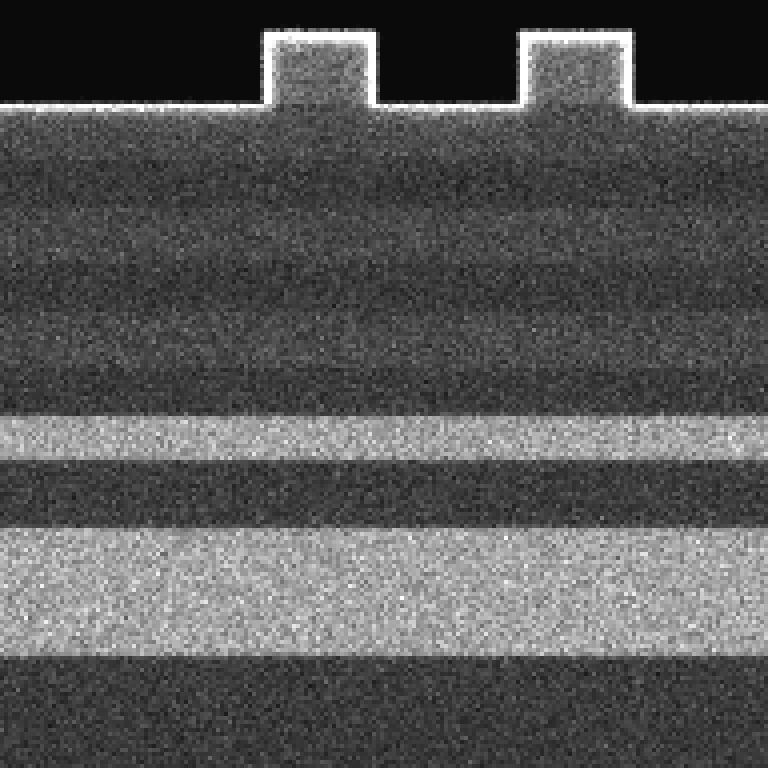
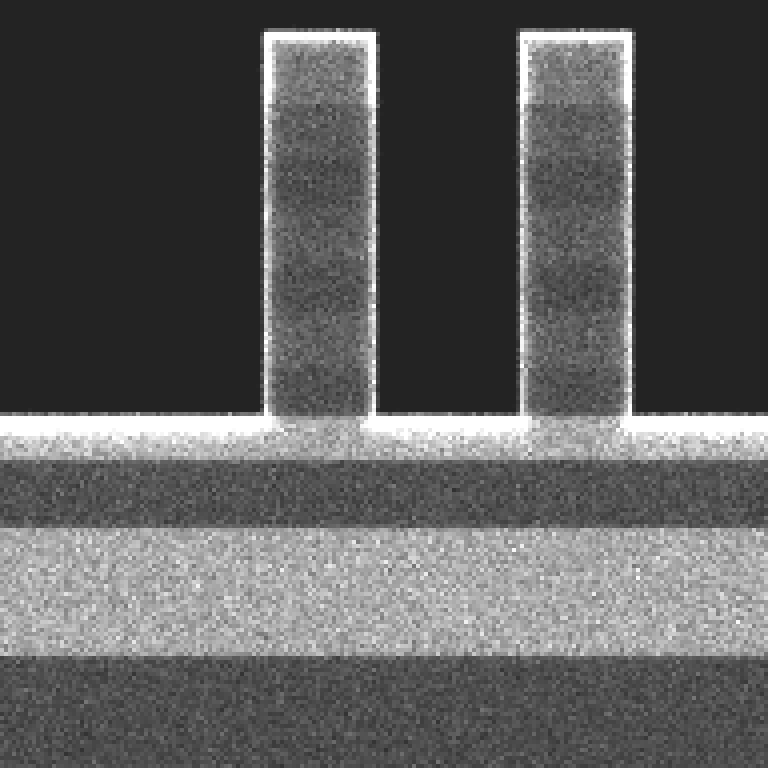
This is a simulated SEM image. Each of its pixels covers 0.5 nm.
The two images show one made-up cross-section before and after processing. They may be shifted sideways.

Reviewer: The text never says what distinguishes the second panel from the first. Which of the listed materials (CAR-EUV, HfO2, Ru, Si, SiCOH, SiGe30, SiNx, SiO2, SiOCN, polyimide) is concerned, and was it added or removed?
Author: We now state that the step removed Si and SiGe30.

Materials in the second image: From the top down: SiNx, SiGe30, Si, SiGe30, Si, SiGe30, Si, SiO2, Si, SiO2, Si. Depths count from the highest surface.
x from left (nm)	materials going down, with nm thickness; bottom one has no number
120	empty 192, SiO2 22, Si 34, SiO2 64, Si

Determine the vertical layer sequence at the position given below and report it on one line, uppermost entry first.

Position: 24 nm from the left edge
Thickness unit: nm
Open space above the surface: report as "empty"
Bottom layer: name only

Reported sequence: empty 192, SiO2 22, Si 34, SiO2 64, Si